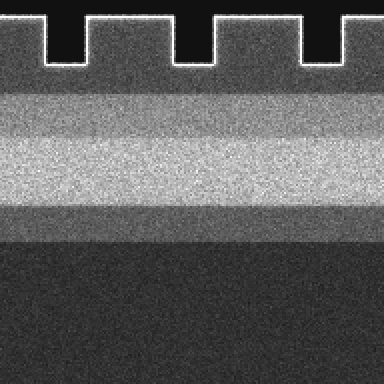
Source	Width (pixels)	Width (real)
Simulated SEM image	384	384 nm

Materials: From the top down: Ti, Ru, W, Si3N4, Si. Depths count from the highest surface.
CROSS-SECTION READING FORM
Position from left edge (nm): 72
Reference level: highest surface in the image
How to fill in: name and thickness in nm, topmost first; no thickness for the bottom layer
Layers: empty 48, Ti 30, Ru 44, W 68, Si3N4 36, Si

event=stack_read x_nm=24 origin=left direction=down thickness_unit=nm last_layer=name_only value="Ti 78, Ru 44, W 68, Si3N4 36, Si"